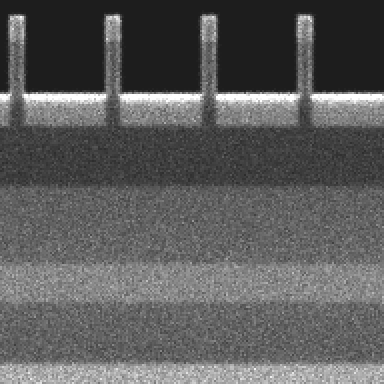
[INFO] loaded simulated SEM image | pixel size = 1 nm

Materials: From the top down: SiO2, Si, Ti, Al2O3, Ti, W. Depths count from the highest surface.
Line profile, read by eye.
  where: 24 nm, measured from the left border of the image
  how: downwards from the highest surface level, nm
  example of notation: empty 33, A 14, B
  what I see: empty 78, SiO2 32, Si 60, Ti 78, Al2O3 38, Ti 62, W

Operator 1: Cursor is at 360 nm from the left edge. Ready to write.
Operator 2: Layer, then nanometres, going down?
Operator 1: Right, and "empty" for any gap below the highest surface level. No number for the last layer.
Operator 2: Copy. empty 78, SiO2 32, Si 60, Ti 78, Al2O3 38, Ti 62, W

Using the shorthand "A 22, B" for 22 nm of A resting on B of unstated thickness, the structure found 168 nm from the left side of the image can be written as empty 78, SiO2 32, Si 60, Ti 78, Al2O3 38, Ti 62, W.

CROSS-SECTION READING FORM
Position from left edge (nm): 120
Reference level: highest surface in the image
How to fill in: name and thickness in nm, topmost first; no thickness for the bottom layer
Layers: empty 78, SiO2 32, Si 60, Ti 78, Al2O3 38, Ti 62, W